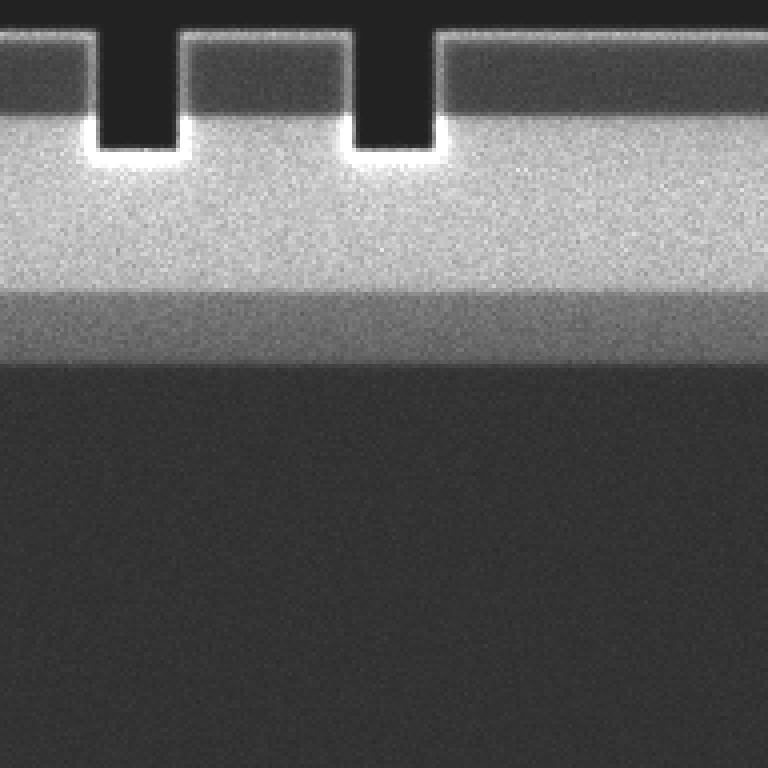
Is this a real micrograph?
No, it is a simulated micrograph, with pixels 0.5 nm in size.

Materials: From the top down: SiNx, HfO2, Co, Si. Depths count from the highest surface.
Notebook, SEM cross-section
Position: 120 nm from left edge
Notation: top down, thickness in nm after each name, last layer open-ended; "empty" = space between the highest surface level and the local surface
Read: SiNx 42, HfO2 88, Co 36, Si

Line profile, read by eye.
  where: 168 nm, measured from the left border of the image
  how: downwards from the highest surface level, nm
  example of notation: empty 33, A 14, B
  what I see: SiNx 42, HfO2 88, Co 36, Si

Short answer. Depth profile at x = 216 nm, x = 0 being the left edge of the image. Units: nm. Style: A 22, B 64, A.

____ empty 60, HfO2 70, Co 36, Si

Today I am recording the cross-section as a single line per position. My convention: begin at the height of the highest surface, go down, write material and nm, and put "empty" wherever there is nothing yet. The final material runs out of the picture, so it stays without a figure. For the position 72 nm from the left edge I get empty 60, HfO2 70, Co 36, Si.